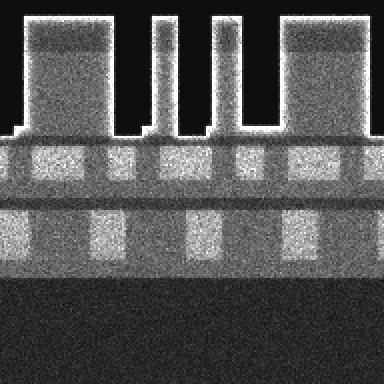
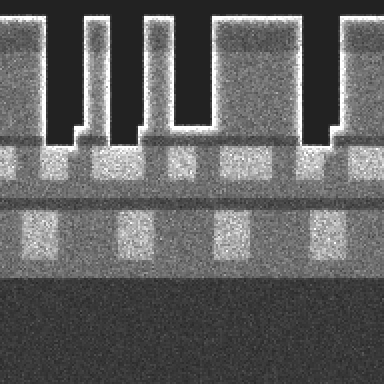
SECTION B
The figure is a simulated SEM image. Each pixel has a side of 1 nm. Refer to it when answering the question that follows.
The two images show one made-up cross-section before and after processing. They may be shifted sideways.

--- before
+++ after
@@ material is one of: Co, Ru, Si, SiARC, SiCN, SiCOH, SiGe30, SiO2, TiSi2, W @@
SiCN removed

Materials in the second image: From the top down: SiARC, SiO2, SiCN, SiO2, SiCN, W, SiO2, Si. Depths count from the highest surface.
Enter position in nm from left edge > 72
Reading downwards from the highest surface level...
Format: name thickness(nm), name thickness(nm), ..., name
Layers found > empty 130, SiO2 52, SiCN 12, SiO2 68, Si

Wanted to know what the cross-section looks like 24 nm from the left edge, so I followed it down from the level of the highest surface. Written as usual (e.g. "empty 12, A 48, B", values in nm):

SiARC 36, SiO2 84, SiCN 10, SiO2 52, SiCN 12, W 50, SiO2 18, Si